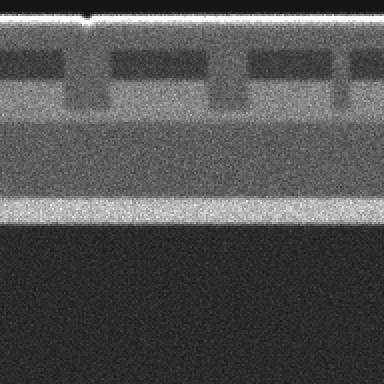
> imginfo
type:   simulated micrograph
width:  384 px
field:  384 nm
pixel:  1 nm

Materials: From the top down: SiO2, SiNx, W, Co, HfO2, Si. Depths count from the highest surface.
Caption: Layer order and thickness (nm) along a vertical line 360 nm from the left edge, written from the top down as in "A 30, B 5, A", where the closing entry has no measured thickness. SiO2 34, SiNx 30, W 42, Co 76, HfO2 26, Si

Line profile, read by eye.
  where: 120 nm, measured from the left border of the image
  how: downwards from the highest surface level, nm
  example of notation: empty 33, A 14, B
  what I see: SiO2 34, SiNx 30, W 42, Co 76, HfO2 26, Si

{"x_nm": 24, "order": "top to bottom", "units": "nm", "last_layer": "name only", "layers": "SiO2 34, SiNx 30, W 42, Co 76, HfO2 26, Si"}